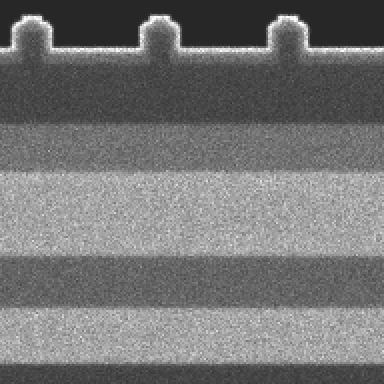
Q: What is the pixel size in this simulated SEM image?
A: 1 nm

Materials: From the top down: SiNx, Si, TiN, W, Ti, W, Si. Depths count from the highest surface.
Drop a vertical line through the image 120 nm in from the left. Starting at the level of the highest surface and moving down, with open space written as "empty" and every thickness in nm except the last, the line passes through empty 32, SiNx 16, Si 60, TiN 48, W 84, Ti 52, W 56, Si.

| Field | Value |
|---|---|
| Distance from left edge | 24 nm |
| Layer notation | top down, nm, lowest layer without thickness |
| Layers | SiNx 16, Si 92, TiN 48, W 84, Ti 52, W 56, Si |